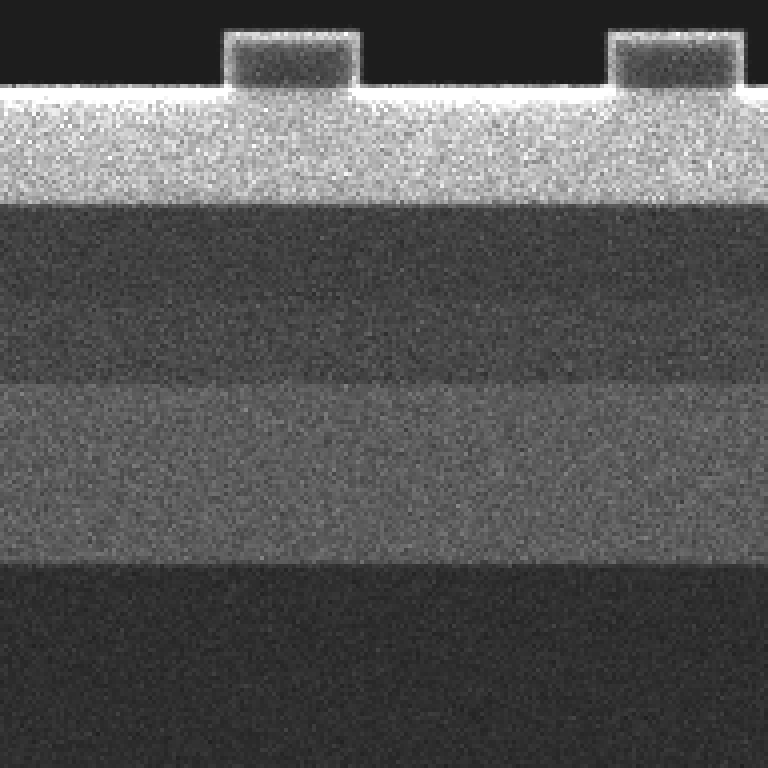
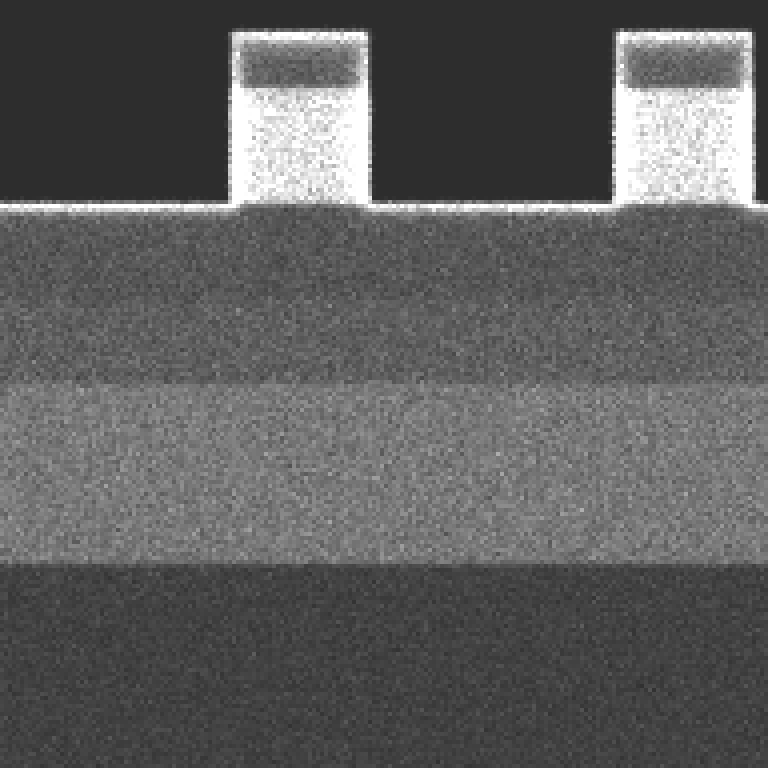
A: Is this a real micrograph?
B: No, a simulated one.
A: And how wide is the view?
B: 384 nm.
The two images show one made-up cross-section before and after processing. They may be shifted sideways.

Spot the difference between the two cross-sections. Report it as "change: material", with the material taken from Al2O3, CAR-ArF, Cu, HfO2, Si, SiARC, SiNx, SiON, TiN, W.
removed: HfO2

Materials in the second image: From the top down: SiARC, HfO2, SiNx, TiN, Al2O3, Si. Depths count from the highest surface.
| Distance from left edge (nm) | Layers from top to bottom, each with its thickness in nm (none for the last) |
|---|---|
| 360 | SiARC 28, HfO2 58, SiNx 48, TiN 42, Al2O3 90, Si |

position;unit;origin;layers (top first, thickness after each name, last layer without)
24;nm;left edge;empty 86, SiNx 48, TiN 42, Al2O3 90, Si